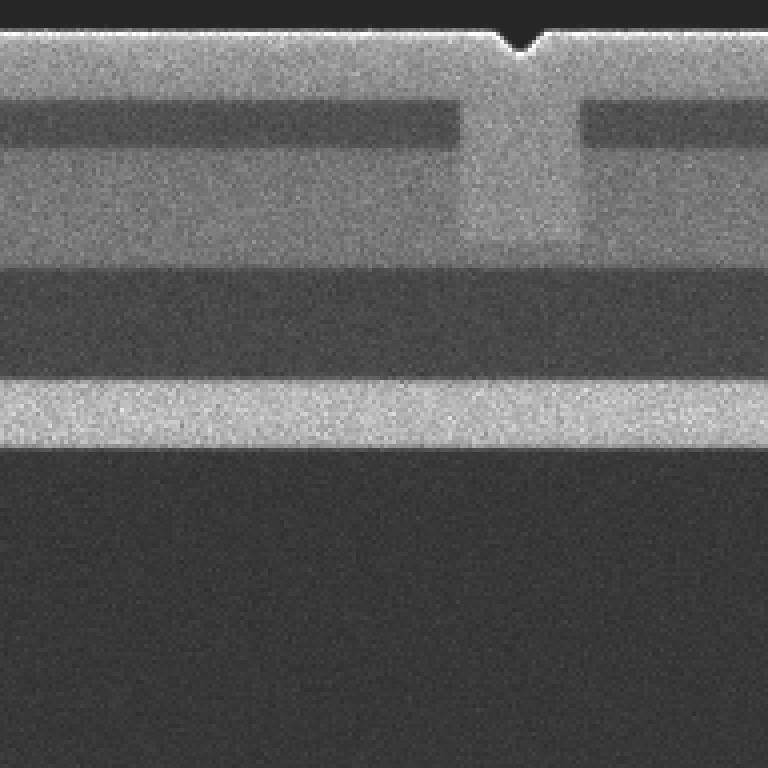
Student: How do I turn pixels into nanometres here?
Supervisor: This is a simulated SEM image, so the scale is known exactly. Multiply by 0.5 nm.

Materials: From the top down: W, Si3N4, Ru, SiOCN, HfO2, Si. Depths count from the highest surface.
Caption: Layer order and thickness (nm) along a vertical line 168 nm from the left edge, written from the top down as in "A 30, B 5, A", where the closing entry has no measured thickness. W 34, Si3N4 24, Ru 60, SiOCN 56, HfO2 34, Si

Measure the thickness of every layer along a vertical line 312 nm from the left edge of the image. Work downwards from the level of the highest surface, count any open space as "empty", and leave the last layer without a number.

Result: W 34, Si3N4 24, Ru 60, SiOCN 56, HfO2 34, Si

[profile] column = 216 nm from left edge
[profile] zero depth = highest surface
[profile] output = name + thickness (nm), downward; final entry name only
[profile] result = W 34, Si3N4 24, Ru 60, SiOCN 56, HfO2 34, Si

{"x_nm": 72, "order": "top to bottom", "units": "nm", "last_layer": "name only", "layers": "W 34, Si3N4 24, Ru 60, SiOCN 56, HfO2 34, Si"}